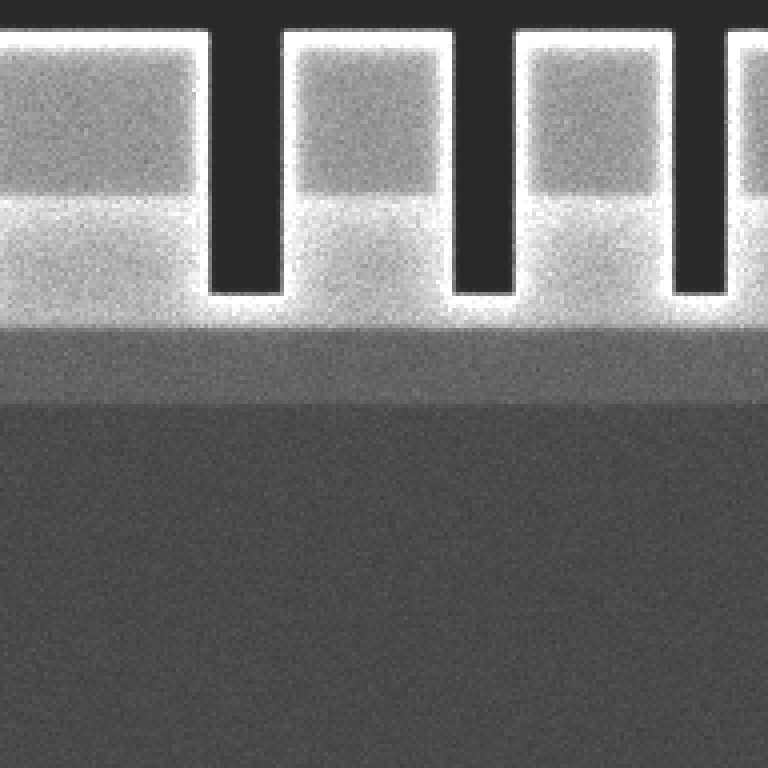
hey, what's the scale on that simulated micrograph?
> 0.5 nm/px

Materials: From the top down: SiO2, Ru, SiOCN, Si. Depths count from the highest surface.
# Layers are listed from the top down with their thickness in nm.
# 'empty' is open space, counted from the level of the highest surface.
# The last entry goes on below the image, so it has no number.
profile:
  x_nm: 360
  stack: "empty 132, Ru 16, SiOCN 38, Si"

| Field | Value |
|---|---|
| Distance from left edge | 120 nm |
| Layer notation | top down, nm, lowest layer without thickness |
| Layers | empty 132, Ru 16, SiOCN 38, Si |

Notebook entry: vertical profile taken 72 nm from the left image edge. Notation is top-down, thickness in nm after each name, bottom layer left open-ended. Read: SiO2 82, Ru 66, SiOCN 38, Si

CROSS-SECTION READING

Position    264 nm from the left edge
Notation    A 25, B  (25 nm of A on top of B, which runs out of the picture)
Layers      SiO2 82, Ru 66, SiOCN 38, Si